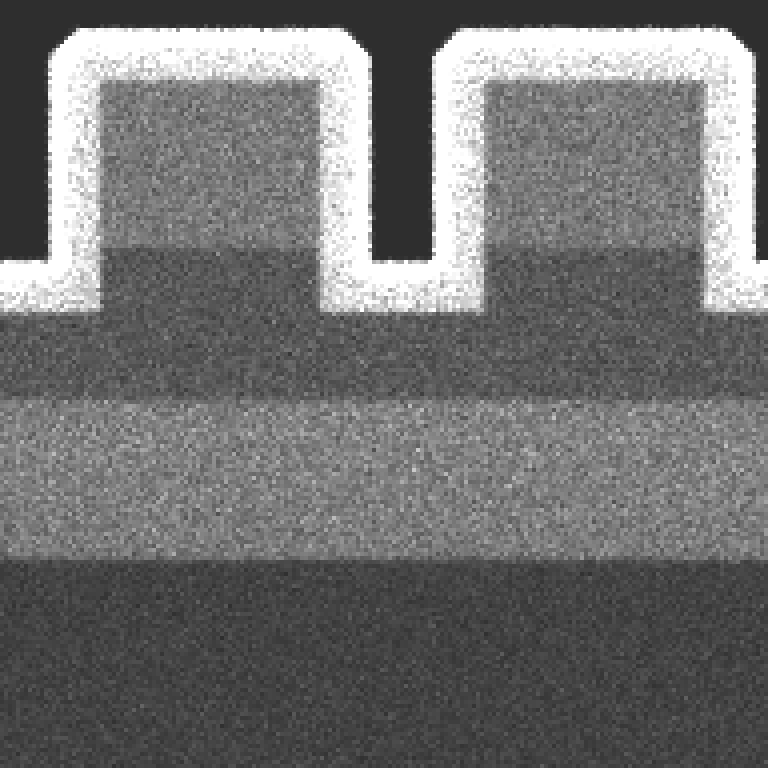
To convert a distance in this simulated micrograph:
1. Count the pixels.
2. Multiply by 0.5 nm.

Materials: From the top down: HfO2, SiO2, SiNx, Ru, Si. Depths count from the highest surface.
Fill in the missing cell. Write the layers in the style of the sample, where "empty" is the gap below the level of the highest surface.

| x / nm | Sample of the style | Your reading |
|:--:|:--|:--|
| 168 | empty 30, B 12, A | HfO2 140, SiNx 44, Ru 80, Si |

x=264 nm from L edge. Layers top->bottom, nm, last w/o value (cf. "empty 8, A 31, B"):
HfO2 24, SiO2 84, SiNx 76, Ru 80, Si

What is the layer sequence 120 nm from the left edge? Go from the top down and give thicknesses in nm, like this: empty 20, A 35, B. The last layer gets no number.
HfO2 24, SiO2 84, SiNx 76, Ru 80, Si